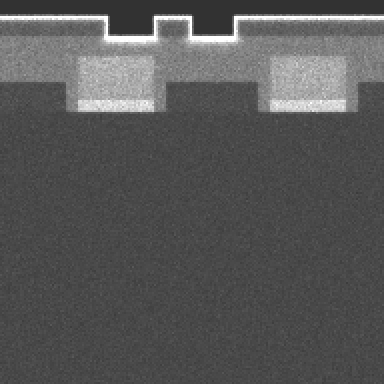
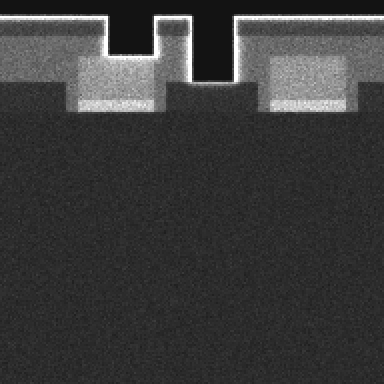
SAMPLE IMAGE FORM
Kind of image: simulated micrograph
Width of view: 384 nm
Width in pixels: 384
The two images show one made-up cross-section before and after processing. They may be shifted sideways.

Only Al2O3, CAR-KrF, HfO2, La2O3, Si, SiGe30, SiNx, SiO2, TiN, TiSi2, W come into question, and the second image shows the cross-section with SiO2 removed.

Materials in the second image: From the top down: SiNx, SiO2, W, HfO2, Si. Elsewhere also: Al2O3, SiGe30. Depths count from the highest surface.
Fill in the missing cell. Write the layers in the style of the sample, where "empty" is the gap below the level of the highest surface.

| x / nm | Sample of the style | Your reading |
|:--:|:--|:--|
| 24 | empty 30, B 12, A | SiNx 20, SiO2 46, SiGe30 30, Si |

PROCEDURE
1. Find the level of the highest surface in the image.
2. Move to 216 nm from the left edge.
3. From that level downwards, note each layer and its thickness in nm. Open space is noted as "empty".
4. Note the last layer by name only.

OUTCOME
empty 66, SiGe30 30, Si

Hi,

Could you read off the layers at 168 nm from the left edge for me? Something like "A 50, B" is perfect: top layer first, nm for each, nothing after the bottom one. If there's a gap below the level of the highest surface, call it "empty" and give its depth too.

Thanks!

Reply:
SiNx 20, SiO2 46, SiGe30 30, Si